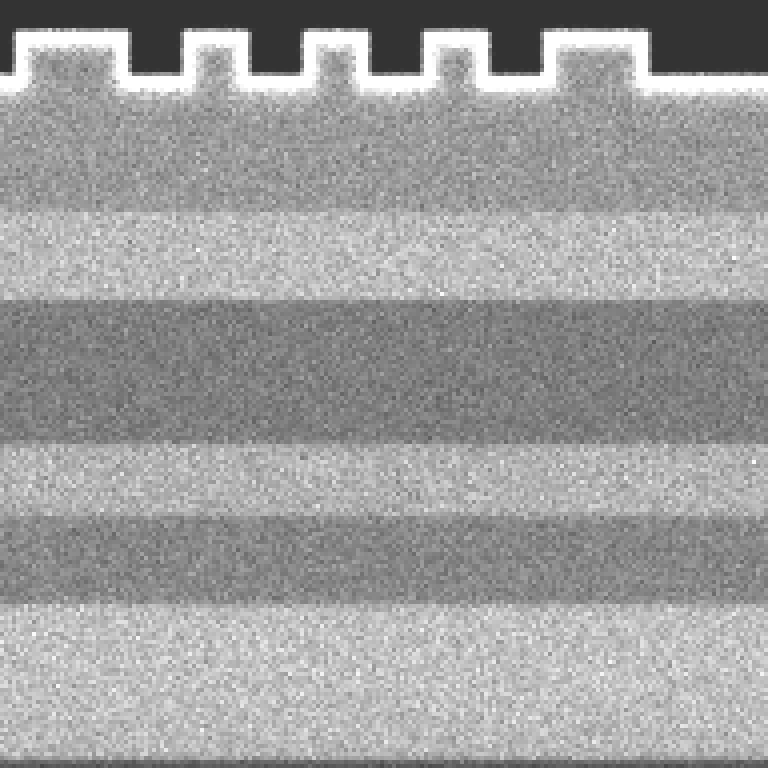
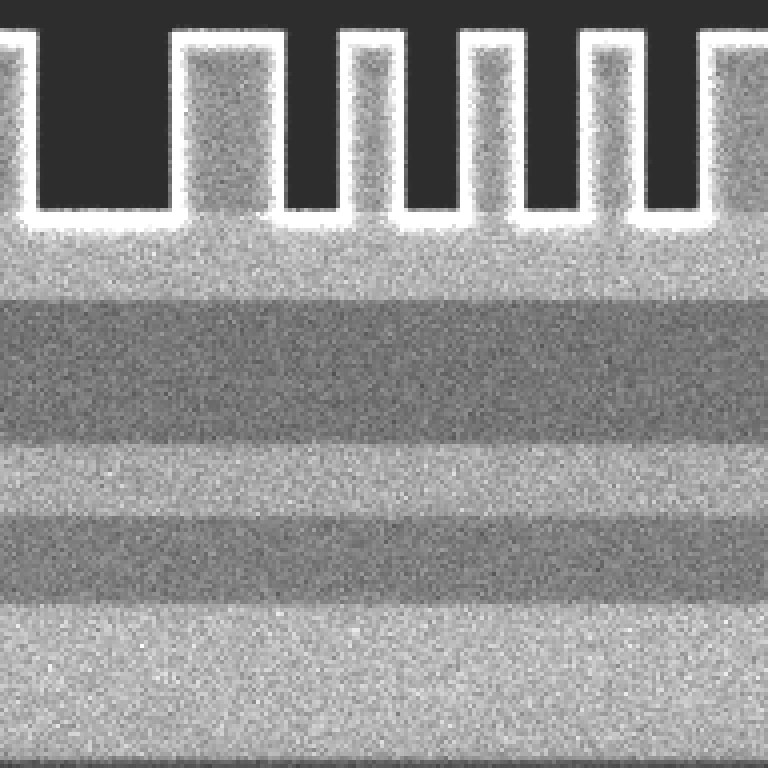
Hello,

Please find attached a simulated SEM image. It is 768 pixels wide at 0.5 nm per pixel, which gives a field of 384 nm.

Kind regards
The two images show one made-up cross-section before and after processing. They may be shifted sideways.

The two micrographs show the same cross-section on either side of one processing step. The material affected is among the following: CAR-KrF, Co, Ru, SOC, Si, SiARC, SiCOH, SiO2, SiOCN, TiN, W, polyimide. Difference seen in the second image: SOC removed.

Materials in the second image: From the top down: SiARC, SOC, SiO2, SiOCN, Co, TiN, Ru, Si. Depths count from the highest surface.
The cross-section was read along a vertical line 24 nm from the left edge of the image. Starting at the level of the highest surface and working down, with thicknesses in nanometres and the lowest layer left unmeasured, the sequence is empty 90, SiO2 44, SiOCN 72, Co 36, TiN 44, Ru 78, Si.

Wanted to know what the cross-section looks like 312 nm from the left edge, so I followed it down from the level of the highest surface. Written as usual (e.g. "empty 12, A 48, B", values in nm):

SiARC 22, SOC 68, SiO2 44, SiOCN 72, Co 36, TiN 44, Ru 78, Si